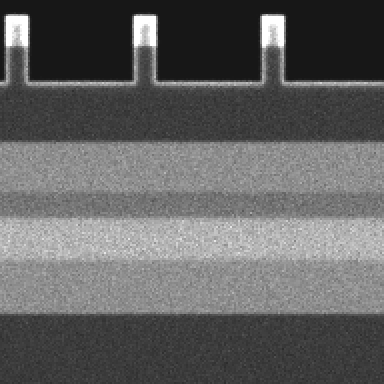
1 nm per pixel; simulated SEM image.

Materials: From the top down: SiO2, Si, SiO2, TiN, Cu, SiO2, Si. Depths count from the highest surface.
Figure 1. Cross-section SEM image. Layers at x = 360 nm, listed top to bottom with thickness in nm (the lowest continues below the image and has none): empty 66, Si 60, SiO2 50, TiN 26, Cu 42, SiO2 54, Si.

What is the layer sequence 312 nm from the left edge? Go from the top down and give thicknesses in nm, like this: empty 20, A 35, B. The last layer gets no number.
empty 66, Si 60, SiO2 50, TiN 26, Cu 42, SiO2 54, Si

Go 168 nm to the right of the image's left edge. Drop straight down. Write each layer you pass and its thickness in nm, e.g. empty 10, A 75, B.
empty 66, Si 60, SiO2 50, TiN 26, Cu 42, SiO2 54, Si